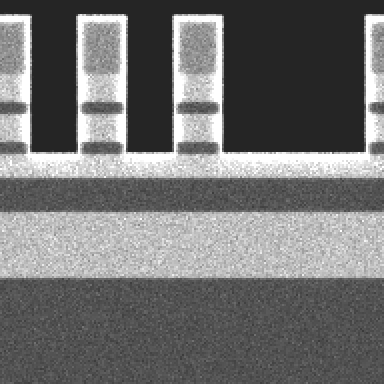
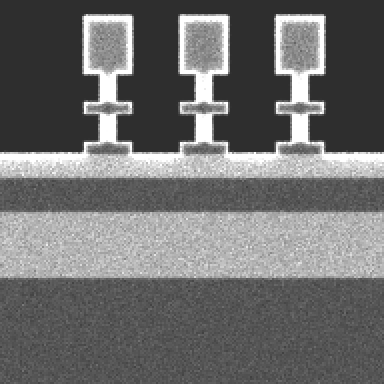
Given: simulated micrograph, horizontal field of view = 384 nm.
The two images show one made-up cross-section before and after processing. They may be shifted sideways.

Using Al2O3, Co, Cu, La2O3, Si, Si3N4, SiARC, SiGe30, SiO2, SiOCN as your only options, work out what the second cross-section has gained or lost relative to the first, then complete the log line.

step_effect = removed SiO2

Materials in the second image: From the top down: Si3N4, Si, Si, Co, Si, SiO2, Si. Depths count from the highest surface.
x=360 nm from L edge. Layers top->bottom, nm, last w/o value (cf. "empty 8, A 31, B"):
empty 138, Co 24, Si 34, SiO2 66, Si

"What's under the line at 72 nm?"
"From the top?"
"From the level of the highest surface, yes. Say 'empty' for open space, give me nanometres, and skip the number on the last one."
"empty 138, Co 24, Si 34, SiO2 66, Si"